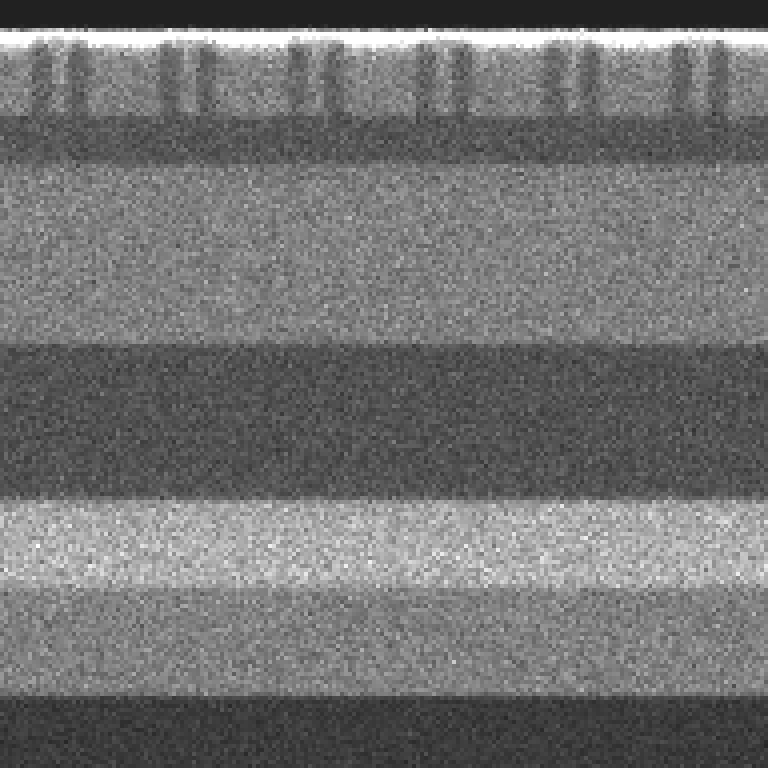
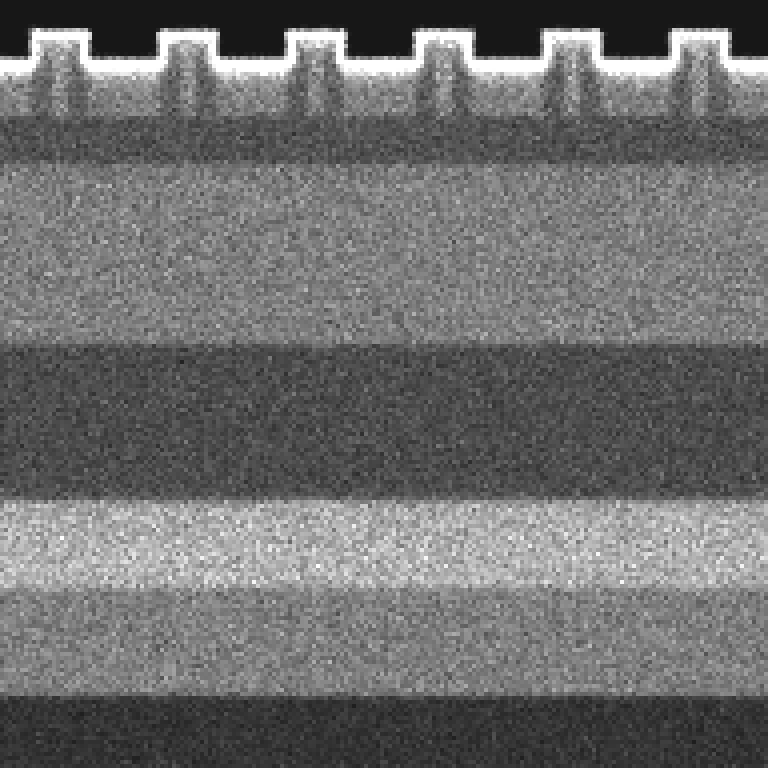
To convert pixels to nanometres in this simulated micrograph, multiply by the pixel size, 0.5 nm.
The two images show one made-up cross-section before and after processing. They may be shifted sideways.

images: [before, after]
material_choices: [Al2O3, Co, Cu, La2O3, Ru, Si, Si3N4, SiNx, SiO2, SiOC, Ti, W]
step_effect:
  removed: SiO2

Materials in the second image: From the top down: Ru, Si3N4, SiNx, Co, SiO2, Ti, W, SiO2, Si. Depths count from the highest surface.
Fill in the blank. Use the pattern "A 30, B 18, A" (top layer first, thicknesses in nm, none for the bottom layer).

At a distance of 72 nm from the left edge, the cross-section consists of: empty 14, SiO2 28, SiNx 24, Co 10, SiO2 80, Ti 78, W 44, SiO2 54, Si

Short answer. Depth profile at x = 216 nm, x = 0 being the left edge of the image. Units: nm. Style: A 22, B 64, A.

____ Ru 10, Si3N4 32, SiNx 24, Co 10, SiO2 80, Ti 78, W 44, SiO2 54, Si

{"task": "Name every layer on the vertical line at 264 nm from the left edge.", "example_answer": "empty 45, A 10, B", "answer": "empty 14, SiO2 28, SiNx 24, Co 10, SiO2 80, Ti 78, W 44, SiO2 54, Si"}